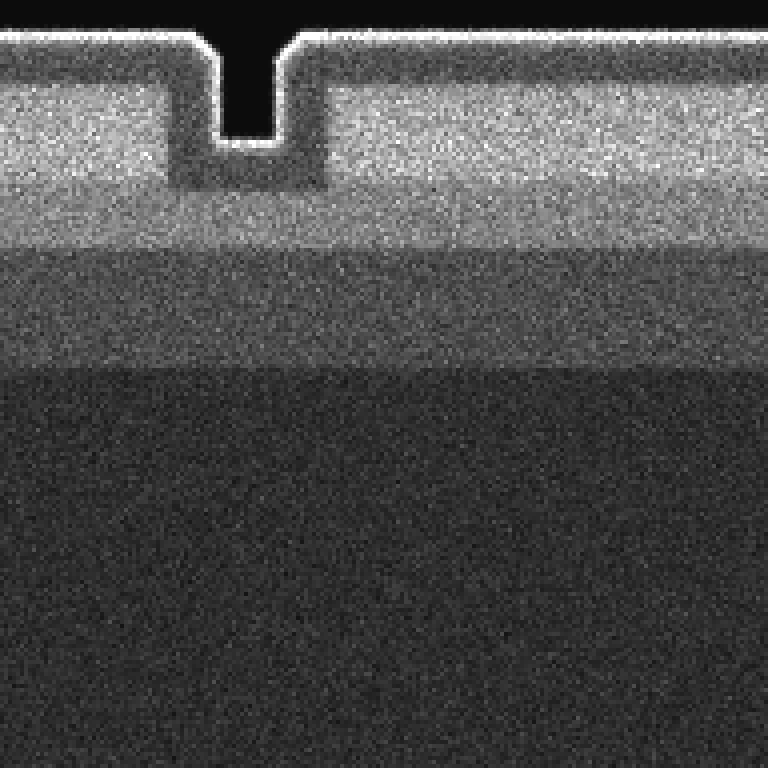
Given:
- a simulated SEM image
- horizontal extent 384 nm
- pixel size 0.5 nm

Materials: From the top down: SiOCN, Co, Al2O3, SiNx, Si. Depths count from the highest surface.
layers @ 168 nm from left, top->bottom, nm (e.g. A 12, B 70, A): SiOCN 26, Co 48, Al2O3 34, SiNx 60, Si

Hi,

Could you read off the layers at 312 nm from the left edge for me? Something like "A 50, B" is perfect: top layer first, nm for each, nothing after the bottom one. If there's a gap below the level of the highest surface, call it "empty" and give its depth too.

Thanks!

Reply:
SiOCN 26, Co 48, Al2O3 34, SiNx 60, Si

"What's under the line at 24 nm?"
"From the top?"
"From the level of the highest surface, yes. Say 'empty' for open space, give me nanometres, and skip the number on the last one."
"SiOCN 26, Co 48, Al2O3 34, SiNx 60, Si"